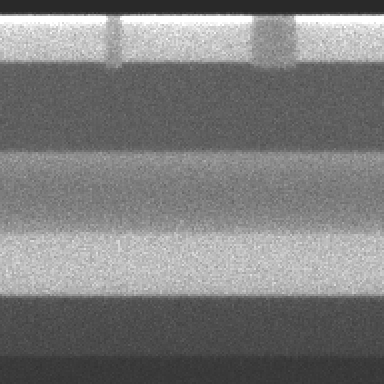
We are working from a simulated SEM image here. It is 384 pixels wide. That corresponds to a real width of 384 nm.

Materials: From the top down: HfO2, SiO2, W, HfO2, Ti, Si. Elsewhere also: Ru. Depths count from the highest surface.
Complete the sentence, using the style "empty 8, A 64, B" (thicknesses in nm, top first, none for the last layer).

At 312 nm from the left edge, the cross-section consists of HfO2 46, SiO2 90, W 82, HfO2 62, Ti 60, Si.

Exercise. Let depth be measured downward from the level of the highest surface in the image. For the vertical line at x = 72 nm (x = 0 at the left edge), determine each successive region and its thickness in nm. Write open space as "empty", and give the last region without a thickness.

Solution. HfO2 46, SiO2 90, W 82, HfO2 62, Ti 60, Si